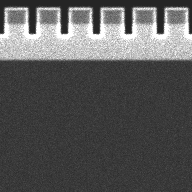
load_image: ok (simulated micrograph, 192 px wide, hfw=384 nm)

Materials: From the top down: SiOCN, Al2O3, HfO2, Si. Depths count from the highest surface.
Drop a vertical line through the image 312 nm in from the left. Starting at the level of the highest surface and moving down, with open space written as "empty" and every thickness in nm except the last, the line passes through empty 54, HfO2 50, Si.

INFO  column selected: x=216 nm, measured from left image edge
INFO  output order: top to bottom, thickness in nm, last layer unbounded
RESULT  SiOCN 8, Al2O3 24, HfO2 72, Si